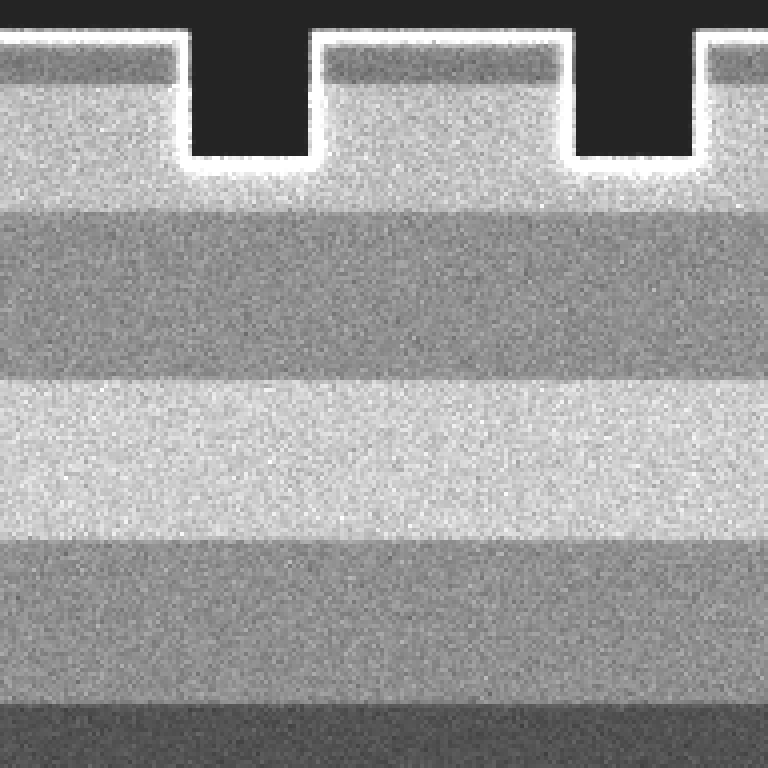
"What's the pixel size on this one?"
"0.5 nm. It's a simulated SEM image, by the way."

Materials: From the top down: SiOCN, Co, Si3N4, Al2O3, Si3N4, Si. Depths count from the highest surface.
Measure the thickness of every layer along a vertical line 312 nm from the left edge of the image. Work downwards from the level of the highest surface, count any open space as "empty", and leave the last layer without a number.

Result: empty 64, Co 26, Si3N4 84, Al2O3 80, Si3N4 82, Si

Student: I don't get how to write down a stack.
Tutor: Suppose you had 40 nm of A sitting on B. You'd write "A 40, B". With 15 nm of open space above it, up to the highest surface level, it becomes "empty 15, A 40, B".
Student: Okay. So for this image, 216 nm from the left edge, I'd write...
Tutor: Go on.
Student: SiOCN 26, Co 64, Si3N4 84, Al2O3 80, Si3N4 82, Si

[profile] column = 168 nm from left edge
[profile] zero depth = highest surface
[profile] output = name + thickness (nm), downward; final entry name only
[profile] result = SiOCN 26, Co 64, Si3N4 84, Al2O3 80, Si3N4 82, Si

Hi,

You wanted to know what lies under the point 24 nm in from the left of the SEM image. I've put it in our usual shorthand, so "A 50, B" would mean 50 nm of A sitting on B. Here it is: SiOCN 26, Co 64, Si3N4 84, Al2O3 80, Si3N4 82, Si